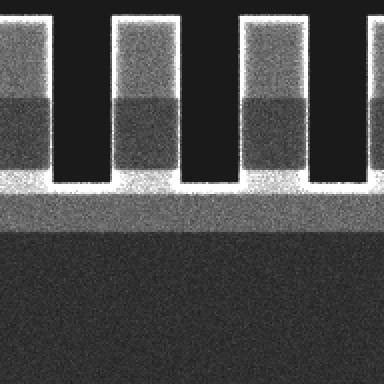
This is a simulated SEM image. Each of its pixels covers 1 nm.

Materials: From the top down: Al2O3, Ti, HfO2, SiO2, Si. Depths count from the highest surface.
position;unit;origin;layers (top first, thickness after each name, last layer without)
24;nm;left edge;Al2O3 82, Ti 72, HfO2 24, SiO2 38, Si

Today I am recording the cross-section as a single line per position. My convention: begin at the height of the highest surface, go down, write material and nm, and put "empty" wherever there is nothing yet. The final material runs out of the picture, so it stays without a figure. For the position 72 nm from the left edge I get empty 168, HfO2 10, SiO2 38, Si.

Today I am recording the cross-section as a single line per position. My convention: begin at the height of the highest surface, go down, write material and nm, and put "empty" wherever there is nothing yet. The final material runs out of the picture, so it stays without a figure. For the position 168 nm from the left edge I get Al2O3 82, Ti 72, HfO2 24, SiO2 38, Si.